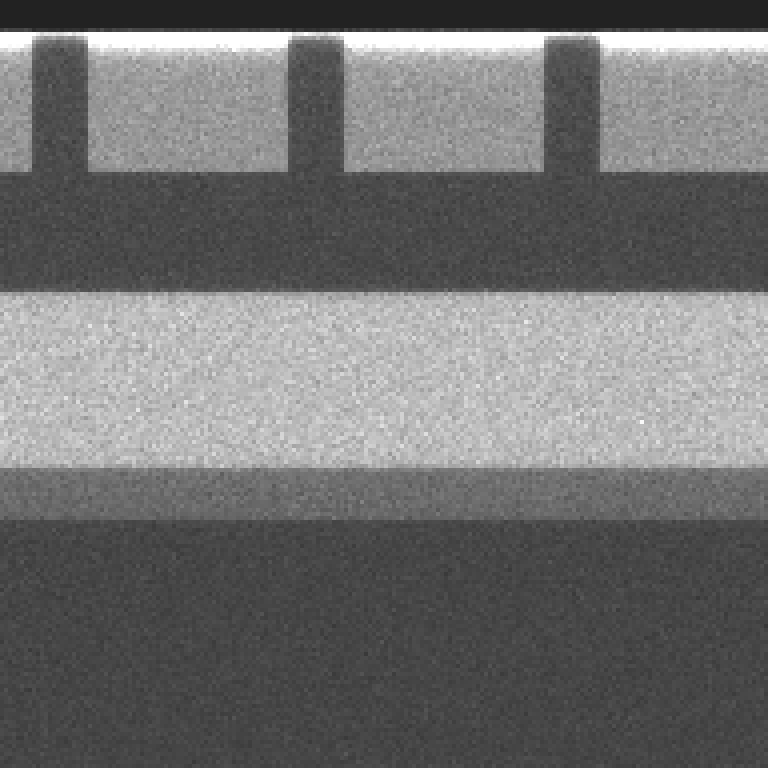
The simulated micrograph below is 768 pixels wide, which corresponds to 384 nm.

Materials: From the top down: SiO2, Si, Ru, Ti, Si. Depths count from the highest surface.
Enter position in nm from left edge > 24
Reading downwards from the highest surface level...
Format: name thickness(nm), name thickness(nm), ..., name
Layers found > Si 130, Ru 88, Ti 26, Si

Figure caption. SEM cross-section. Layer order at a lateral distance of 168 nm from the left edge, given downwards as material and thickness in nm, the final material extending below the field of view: Si 130, Ru 88, Ti 26, Si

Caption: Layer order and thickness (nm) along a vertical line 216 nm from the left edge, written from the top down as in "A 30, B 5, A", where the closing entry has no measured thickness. SiO2 70, Si 60, Ru 88, Ti 26, Si